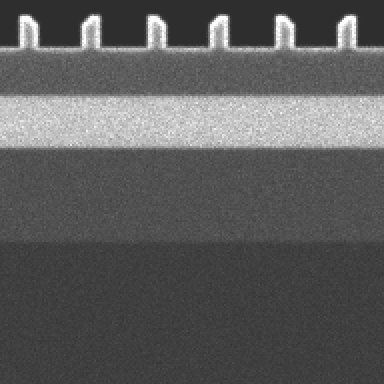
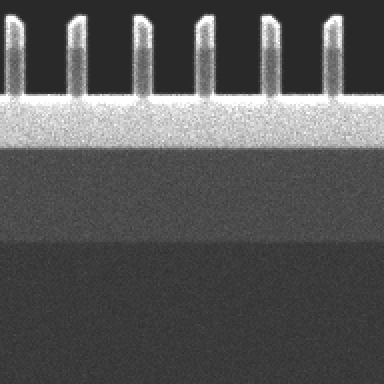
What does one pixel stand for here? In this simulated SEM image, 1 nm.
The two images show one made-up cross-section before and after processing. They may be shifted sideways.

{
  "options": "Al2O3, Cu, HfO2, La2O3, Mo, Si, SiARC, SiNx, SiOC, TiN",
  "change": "removed",
  "material": "TiN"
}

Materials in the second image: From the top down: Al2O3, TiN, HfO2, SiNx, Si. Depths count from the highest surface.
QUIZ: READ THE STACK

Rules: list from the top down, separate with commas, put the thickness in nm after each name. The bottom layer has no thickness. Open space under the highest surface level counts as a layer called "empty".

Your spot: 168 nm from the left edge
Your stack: empty 80, HfO2 52, SiNx 94, Si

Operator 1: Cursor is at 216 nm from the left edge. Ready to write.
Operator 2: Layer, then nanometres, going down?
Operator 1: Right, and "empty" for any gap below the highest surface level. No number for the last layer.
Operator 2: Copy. empty 80, HfO2 52, SiNx 94, Si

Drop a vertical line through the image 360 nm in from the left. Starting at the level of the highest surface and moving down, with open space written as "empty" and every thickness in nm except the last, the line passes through empty 80, HfO2 52, SiNx 94, Si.